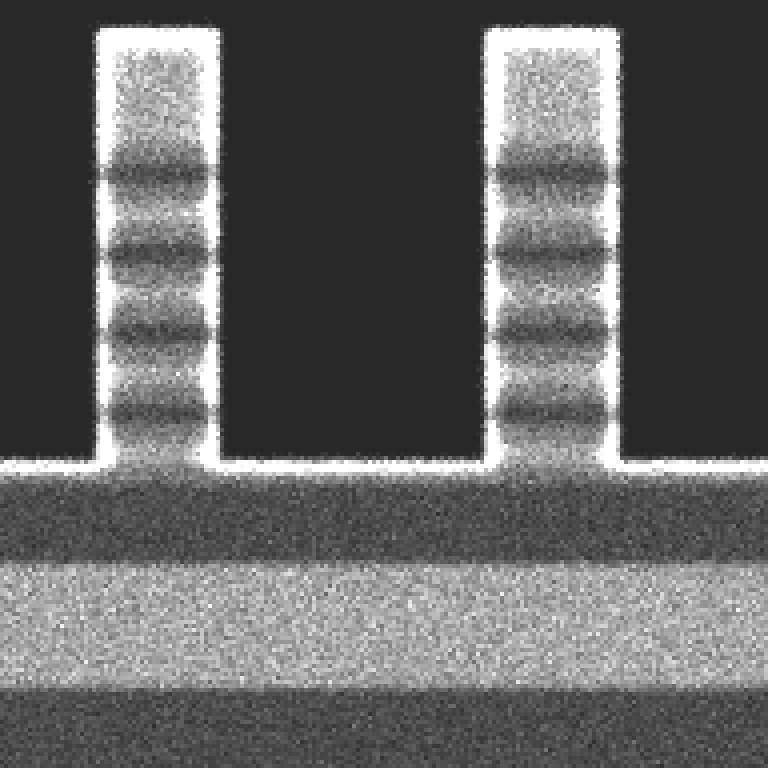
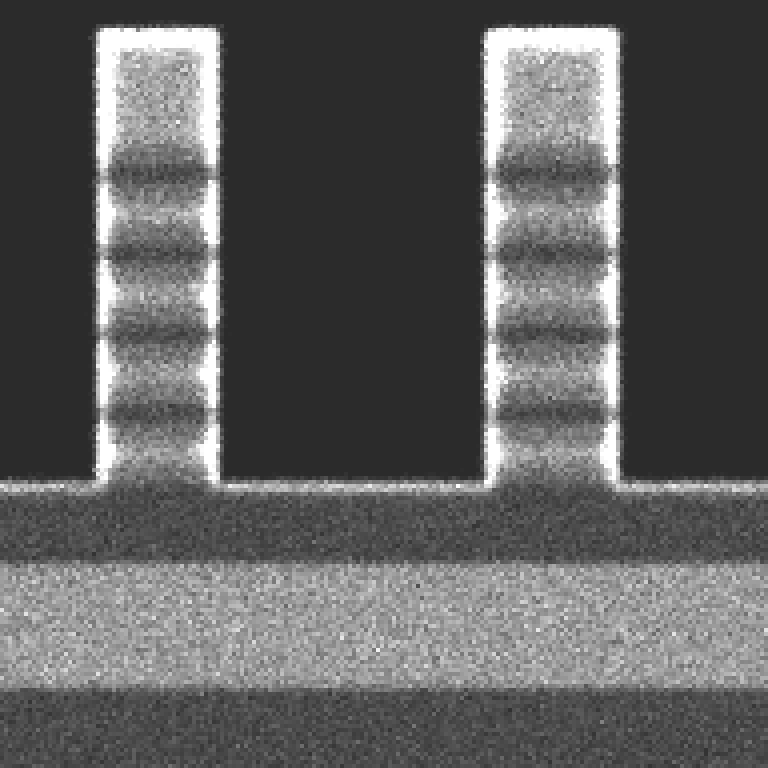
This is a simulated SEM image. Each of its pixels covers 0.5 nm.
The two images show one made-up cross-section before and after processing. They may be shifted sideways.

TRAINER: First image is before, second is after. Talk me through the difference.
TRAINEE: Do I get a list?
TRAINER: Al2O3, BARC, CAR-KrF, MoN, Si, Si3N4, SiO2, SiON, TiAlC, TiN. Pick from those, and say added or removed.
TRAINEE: removed: TiN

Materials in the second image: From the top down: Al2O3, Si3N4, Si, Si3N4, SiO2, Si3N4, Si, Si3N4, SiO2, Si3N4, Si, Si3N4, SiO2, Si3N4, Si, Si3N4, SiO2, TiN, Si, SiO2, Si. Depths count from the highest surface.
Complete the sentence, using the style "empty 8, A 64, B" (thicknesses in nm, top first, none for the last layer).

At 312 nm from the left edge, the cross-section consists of empty 226, Si 40, SiO2 62, Si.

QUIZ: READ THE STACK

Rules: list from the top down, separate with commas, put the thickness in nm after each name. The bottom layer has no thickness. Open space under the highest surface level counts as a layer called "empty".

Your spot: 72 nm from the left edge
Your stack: Al2O3 56, Si3N4 10, Si 10, Si3N4 10, SiO2 10, Si3N4 10, Si 10, Si3N4 10, SiO2 10, Si3N4 10, Si 10, Si3N4 10, SiO2 10, Si3N4 10, Si 10, Si3N4 10, SiO2 10, TiN 10, Si 40, SiO2 62, Si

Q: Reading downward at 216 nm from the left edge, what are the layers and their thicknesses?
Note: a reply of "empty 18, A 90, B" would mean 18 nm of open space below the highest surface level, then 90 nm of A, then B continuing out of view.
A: empty 226, Si 40, SiO2 62, Si